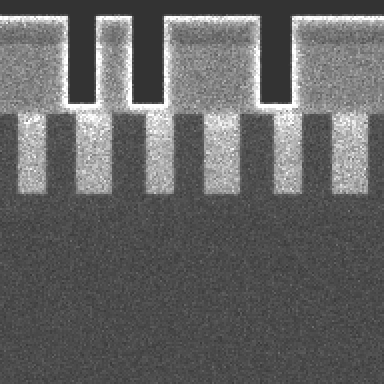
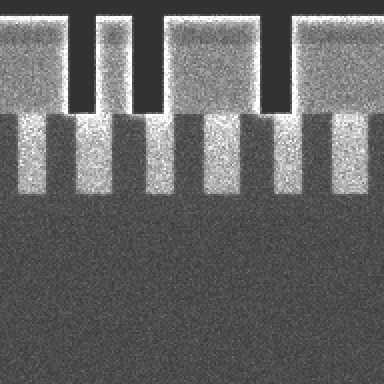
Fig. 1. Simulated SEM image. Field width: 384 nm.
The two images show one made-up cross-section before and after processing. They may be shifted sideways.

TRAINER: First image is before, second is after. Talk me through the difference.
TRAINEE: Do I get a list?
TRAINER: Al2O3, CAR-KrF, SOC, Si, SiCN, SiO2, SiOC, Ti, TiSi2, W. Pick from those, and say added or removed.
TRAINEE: removed: Al2O3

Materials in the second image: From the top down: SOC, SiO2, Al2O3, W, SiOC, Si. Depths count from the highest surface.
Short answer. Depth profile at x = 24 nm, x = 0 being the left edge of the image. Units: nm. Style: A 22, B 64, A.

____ SOC 28, SiO2 60, Al2O3 10, W 80, SiOC 22, Si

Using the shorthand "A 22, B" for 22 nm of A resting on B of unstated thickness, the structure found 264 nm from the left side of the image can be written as empty 98, SiOC 102, Si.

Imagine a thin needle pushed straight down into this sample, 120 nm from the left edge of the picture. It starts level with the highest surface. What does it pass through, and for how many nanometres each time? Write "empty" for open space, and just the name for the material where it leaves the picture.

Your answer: SOC 28, SiO2 60, Al2O3 10, SiOC 102, Si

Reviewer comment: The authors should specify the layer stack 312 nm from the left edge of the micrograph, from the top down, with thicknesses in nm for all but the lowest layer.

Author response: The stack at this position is SOC 28, SiO2 60, Al2O3 10, SiOC 102, Si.